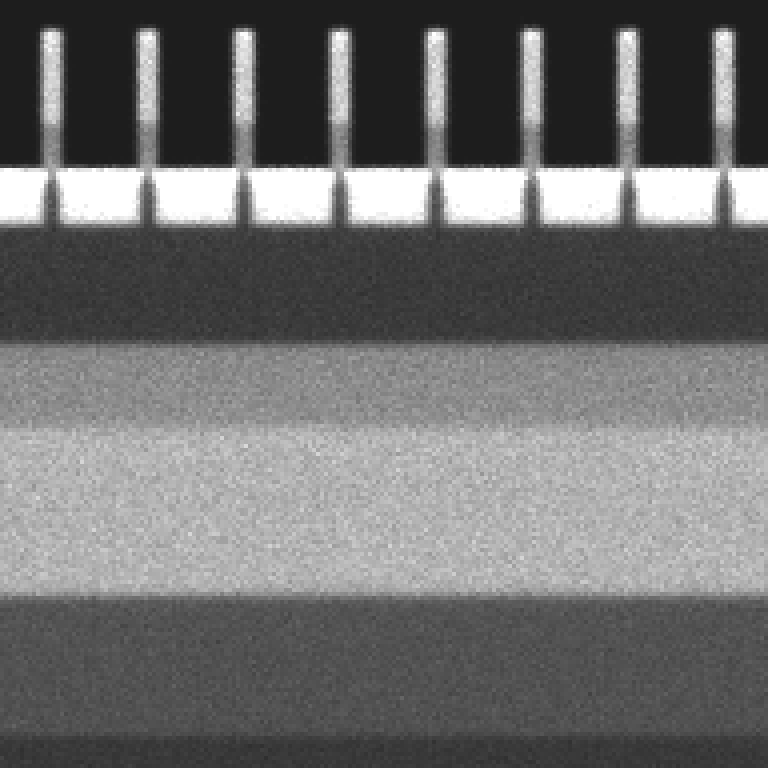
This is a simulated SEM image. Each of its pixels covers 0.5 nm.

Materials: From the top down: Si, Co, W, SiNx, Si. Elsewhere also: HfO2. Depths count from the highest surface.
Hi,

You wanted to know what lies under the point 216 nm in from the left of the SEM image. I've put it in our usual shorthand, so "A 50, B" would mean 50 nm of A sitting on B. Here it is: Si 156, Co 42, W 84, SiNx 70, Si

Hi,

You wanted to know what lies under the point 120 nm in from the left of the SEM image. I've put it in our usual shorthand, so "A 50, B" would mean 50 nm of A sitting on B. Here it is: Si 156, Co 42, W 84, SiNx 70, Si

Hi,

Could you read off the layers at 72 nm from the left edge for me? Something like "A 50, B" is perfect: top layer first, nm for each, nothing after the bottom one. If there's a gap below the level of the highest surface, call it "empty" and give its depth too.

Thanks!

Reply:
Si 156, Co 42, W 84, SiNx 70, Si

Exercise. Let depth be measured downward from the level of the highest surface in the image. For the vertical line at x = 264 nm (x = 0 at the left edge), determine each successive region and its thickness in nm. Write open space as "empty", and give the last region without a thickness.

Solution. Si 156, Co 42, W 84, SiNx 70, Si